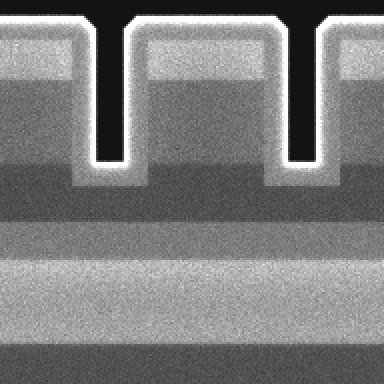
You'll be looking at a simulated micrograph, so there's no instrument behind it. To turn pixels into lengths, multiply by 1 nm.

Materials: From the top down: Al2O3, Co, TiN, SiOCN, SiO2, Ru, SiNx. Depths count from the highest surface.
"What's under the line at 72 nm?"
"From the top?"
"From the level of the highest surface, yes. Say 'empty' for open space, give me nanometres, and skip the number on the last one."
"Al2O3 170, SiOCN 36, SiO2 38, Ru 84, SiNx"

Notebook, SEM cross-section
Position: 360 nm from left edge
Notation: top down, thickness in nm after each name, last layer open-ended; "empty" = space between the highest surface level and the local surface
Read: Al2O3 24, Co 40, TiN 84, SiOCN 58, SiO2 38, Ru 84, SiNx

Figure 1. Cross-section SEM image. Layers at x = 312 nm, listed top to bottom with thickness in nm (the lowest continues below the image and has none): empty 146, Al2O3 24, SiOCN 36, SiO2 38, Ru 84, SiNx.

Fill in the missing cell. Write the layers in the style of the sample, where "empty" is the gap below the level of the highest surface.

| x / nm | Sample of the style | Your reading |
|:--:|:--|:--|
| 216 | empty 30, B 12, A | Al2O3 24, Co 40, TiN 84, SiOCN 58, SiO2 38, Ru 84, SiNx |